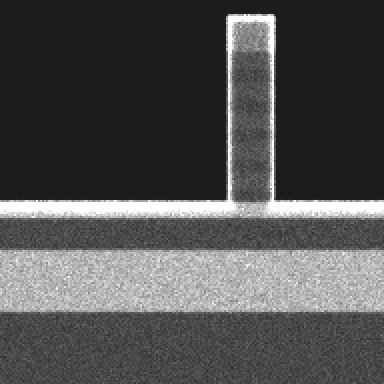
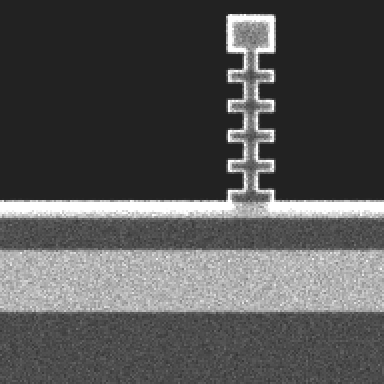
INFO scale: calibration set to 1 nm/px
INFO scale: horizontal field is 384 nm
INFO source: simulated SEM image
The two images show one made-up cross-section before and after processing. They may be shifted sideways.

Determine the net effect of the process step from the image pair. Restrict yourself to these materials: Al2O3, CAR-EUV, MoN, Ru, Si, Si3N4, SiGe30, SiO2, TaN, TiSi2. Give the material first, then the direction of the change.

SiGe30: removed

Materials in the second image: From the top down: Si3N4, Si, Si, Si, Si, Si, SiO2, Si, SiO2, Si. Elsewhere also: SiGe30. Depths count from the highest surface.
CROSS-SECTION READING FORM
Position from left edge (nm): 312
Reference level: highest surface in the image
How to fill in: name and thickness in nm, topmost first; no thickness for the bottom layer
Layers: empty 186, SiO2 16, Si 32, SiO2 62, Si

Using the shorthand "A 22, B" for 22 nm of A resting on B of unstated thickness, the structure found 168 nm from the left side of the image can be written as empty 186, SiO2 16, Si 32, SiO2 62, Si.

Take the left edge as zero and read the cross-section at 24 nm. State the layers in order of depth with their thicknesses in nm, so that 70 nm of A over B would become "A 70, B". empty 186, SiO2 16, Si 32, SiO2 62, Si